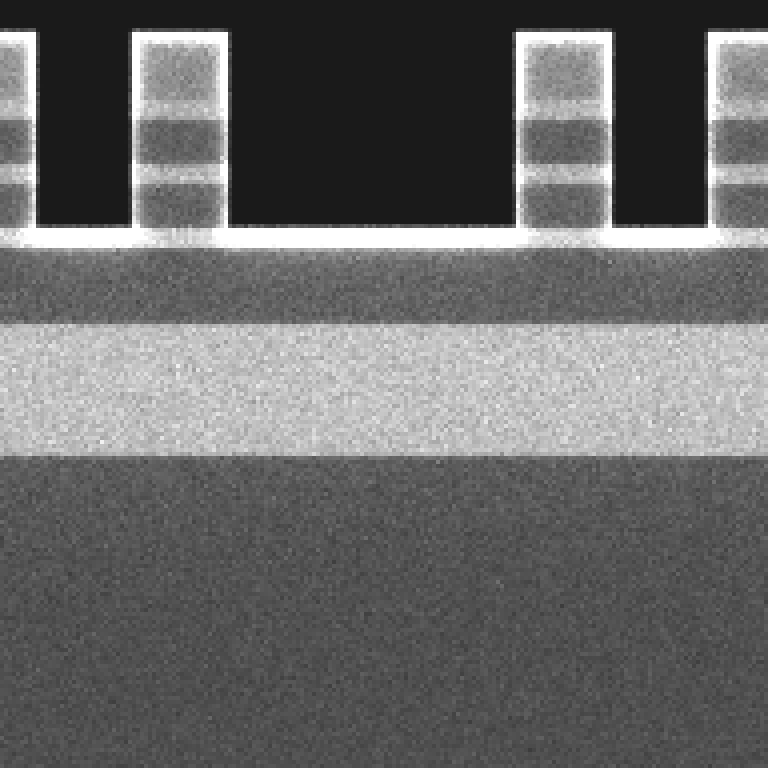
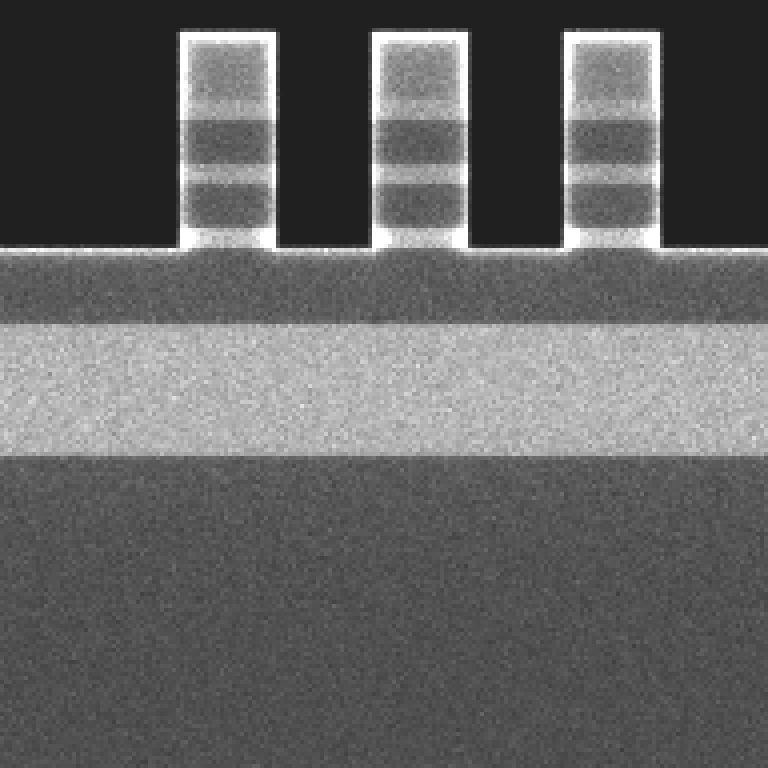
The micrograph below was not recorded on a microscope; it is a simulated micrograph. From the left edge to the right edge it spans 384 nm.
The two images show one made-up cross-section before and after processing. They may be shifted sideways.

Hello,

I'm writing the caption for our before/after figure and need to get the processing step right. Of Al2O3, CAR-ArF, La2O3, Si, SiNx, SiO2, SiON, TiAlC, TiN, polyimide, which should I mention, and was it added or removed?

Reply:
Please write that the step removed Al2O3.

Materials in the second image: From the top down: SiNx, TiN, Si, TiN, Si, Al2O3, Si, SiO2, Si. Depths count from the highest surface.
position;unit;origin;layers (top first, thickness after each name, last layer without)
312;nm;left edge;SiNx 34, TiN 10, Si 22, TiN 10, Si 22, Al2O3 10, Si 38, SiO2 66, Si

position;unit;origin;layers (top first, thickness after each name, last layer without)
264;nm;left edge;empty 108, Si 38, SiO2 66, Si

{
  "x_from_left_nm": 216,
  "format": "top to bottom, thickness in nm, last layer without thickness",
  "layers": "SiNx 34, TiN 10, Si 22, TiN 10, Si 22, Al2O3 10, Si 38, SiO2 66, Si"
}